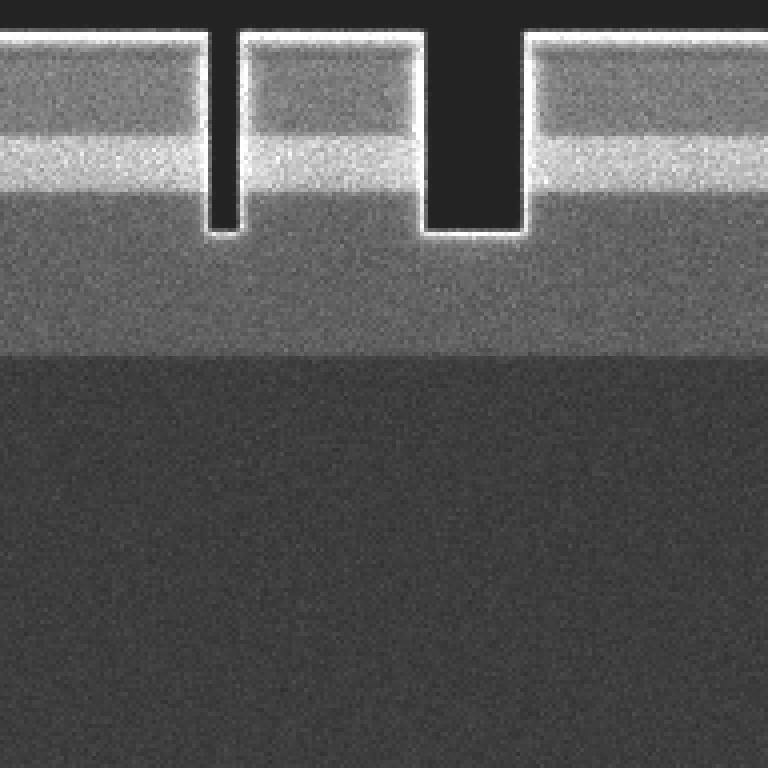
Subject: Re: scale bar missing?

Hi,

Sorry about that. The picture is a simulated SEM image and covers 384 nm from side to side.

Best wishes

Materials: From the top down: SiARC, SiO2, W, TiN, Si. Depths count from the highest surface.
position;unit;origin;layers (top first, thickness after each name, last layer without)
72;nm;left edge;SiARC 14, SiO2 38, W 28, TiN 82, Si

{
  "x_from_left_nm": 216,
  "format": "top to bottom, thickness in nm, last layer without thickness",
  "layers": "empty 100, TiN 62, Si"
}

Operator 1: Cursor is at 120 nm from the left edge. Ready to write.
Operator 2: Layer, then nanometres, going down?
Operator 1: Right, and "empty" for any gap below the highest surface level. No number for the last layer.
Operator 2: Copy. SiARC 14, SiO2 38, W 28, TiN 82, Si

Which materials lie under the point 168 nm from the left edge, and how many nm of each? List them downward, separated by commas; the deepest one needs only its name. SiARC 14, SiO2 38, W 28, TiN 82, Si